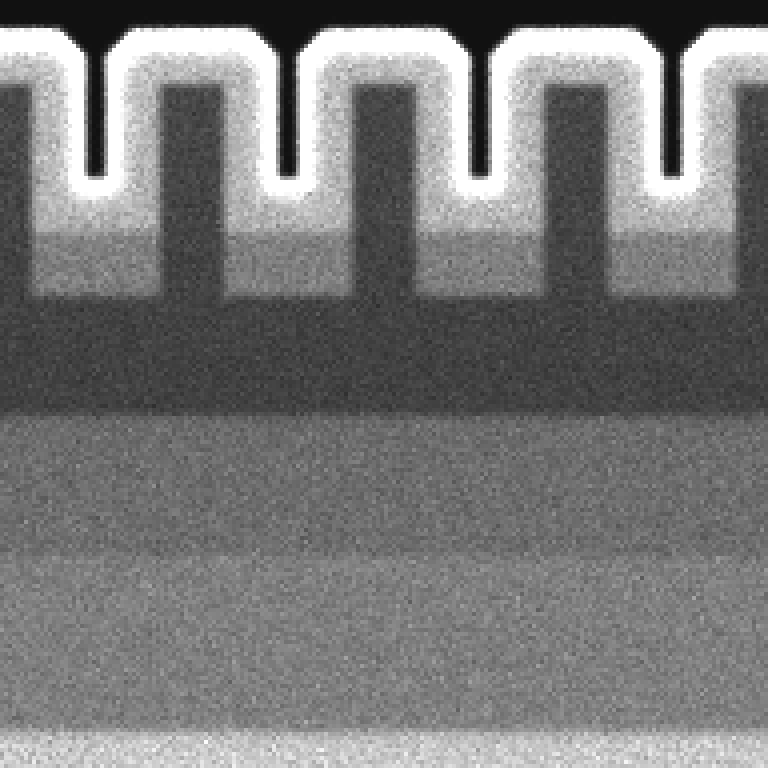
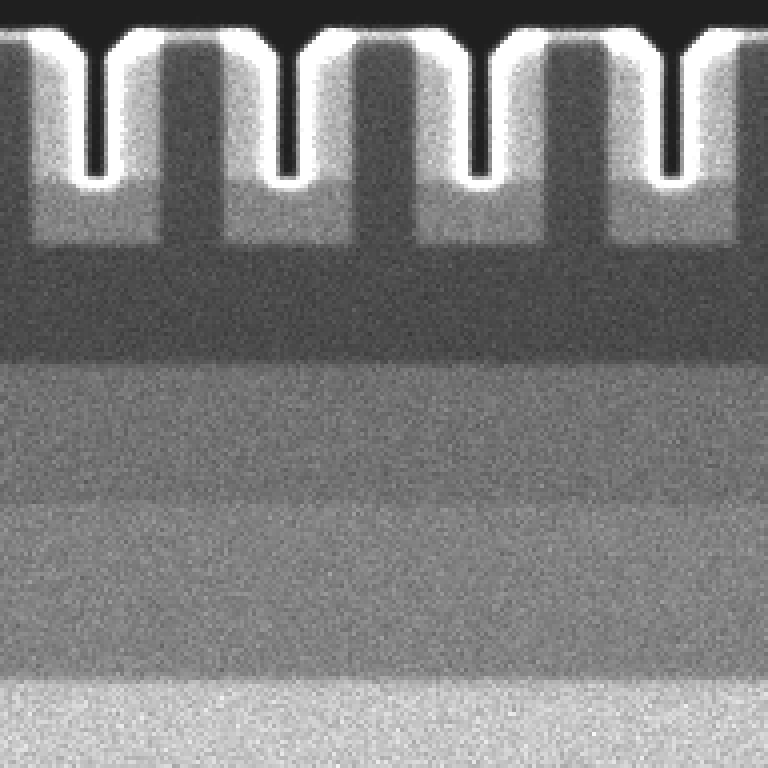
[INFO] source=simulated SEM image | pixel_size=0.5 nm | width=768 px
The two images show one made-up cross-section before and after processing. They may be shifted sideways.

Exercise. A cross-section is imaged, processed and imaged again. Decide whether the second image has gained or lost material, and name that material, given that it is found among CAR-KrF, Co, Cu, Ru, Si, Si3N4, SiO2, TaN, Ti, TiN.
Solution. removed: SiO2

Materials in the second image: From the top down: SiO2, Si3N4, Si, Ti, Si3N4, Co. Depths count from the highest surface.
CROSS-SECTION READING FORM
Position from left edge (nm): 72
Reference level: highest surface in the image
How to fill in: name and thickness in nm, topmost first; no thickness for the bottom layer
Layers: SiO2 74, Si3N4 32, Si 60, Ti 70, Si3N4 88, Co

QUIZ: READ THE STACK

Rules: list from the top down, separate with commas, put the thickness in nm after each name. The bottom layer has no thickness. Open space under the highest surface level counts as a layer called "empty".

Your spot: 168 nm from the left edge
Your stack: SiO2 74, Si3N4 32, Si 60, Ti 70, Si3N4 88, Co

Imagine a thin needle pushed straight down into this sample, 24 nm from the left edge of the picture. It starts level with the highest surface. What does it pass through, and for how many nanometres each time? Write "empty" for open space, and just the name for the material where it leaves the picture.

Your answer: SiO2 74, Si3N4 32, Si 60, Ti 70, Si3N4 88, Co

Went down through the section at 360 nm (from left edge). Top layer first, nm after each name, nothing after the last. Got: SiO2 74, Si3N4 32, Si 60, Ti 70, Si3N4 88, Co